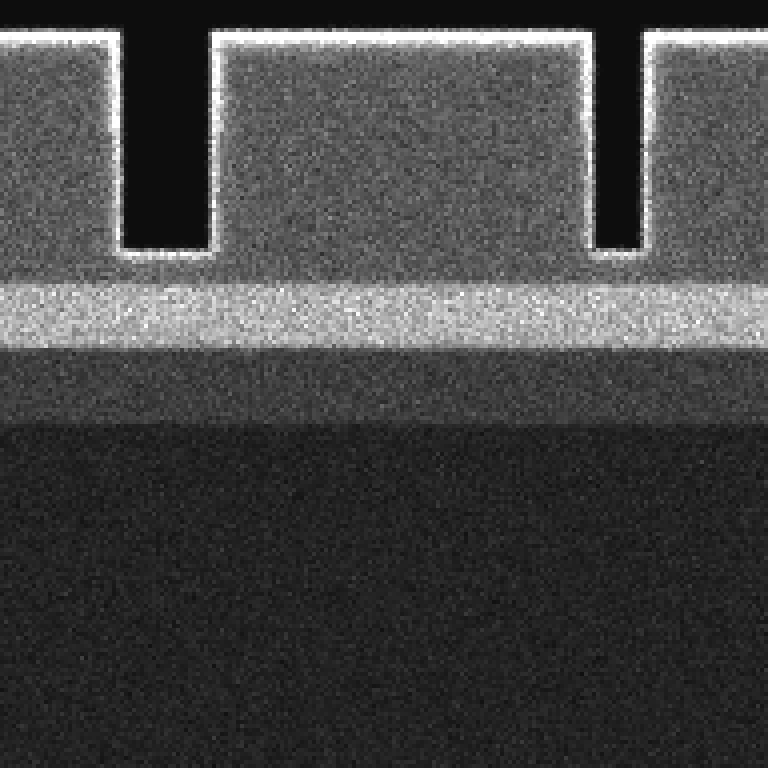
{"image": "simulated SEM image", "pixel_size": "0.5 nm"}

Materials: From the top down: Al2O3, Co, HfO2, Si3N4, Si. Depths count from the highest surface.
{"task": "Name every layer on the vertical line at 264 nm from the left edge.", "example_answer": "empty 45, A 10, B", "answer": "Al2O3 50, Co 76, HfO2 32, Si3N4 38, Si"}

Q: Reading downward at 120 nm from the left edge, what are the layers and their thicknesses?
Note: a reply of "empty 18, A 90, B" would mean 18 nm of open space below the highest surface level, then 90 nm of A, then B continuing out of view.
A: Al2O3 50, Co 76, HfO2 32, Si3N4 38, Si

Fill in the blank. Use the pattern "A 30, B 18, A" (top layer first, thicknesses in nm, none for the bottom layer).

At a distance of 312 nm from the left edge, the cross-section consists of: empty 110, Co 16, HfO2 32, Si3N4 38, Si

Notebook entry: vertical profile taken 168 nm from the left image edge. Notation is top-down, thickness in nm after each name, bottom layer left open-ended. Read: Al2O3 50, Co 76, HfO2 32, Si3N4 38, Si